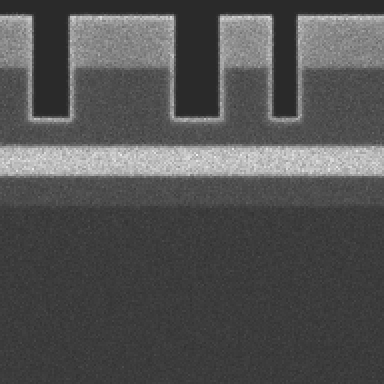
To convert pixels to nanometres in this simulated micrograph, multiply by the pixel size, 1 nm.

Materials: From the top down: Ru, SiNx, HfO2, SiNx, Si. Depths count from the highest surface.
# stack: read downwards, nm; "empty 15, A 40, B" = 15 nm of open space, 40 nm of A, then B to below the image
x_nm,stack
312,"Ru 52, SiNx 78, HfO2 30, SiNx 30, Si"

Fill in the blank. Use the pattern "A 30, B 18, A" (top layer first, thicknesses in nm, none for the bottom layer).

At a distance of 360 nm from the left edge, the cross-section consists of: Ru 52, SiNx 78, HfO2 30, SiNx 30, Si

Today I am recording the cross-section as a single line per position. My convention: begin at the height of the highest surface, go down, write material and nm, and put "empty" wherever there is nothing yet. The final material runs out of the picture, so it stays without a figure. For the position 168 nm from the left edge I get Ru 52, SiNx 78, HfO2 30, SiNx 30, Si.